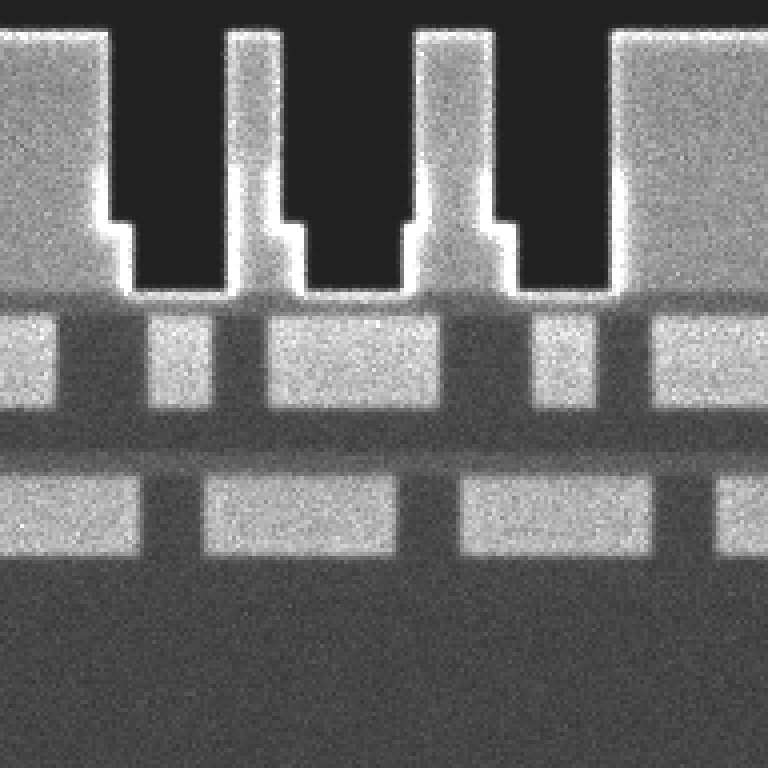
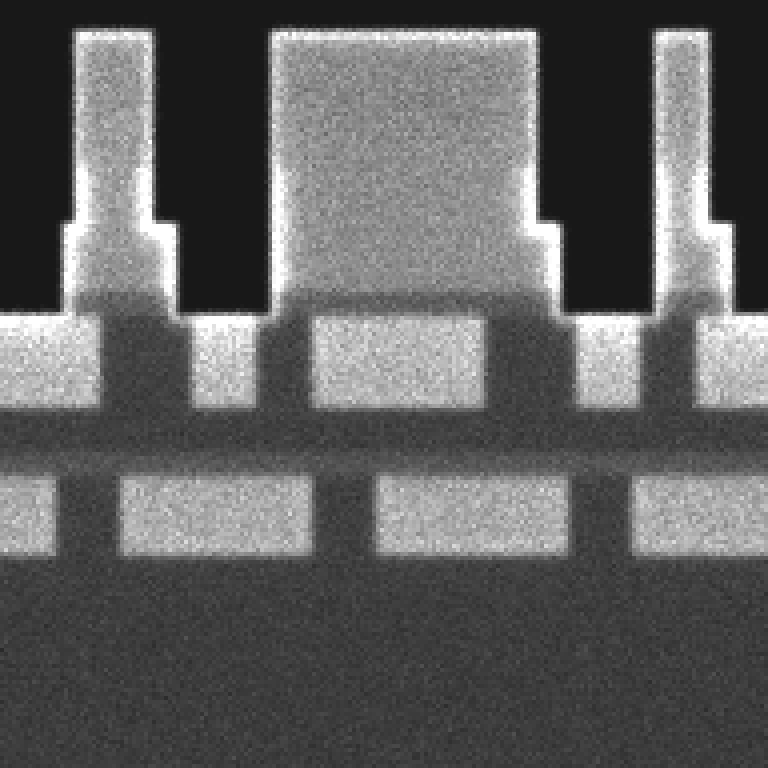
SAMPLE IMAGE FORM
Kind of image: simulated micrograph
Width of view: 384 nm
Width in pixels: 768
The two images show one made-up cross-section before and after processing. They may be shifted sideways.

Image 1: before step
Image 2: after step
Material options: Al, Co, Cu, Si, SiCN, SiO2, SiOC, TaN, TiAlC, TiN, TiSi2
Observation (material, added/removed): SiCN, removed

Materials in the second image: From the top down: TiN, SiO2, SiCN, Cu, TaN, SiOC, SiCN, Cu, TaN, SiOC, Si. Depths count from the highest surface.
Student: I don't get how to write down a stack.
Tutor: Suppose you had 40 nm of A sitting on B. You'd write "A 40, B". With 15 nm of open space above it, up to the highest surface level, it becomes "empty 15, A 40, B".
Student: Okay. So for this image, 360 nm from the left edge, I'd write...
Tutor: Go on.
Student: empty 96, SiO2 34, SiCN 12, Cu 38, TaN 8, SiOC 22, SiCN 12, Cu 32, TaN 8, SiOC 22, Si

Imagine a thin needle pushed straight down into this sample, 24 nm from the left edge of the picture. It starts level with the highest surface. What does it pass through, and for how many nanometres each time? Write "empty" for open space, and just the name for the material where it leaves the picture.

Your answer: empty 142, Cu 38, TaN 8, SiOC 22, SiCN 12, TaN 40, SiOC 22, Si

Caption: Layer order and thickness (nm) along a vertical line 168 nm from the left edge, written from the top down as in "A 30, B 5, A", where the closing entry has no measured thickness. TiN 68, SiO2 62, SiCN 12, Cu 38, TaN 8, SiOC 22, SiCN 12, SiOC 62, Si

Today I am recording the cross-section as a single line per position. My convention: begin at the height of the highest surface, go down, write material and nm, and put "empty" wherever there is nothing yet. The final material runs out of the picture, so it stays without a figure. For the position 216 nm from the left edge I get TiN 68, SiO2 62, SiCN 12, Cu 38, TaN 8, SiOC 22, SiCN 12, Cu 32, TaN 8, SiOC 22, Si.